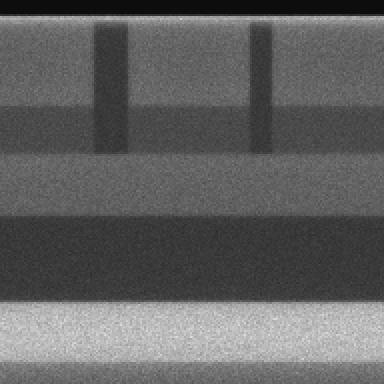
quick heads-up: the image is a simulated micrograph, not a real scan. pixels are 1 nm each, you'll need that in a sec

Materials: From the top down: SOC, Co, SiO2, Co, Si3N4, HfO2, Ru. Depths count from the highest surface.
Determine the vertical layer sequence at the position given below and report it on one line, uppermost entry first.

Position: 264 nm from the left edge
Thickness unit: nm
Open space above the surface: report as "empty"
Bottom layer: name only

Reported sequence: SOC 138, Co 62, Si3N4 86, HfO2 60, Ru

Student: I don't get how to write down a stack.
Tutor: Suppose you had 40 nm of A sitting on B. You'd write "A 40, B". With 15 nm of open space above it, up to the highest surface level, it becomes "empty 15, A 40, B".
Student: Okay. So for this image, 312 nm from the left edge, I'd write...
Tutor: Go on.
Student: SOC 6, Co 84, SiO2 48, Co 62, Si3N4 86, HfO2 60, Ru